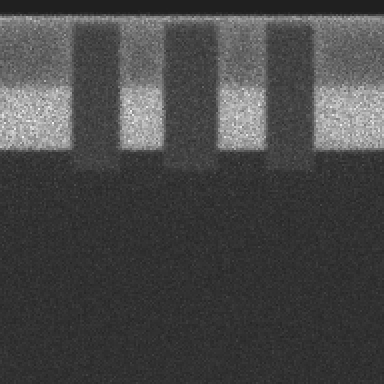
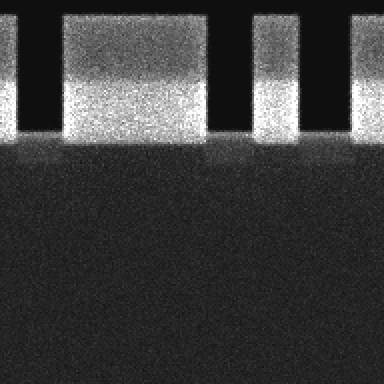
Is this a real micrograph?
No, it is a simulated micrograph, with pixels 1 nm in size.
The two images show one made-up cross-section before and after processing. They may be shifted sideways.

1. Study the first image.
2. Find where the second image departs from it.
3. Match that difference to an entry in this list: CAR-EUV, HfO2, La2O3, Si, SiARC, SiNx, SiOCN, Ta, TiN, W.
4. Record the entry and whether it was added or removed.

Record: SiARC / removed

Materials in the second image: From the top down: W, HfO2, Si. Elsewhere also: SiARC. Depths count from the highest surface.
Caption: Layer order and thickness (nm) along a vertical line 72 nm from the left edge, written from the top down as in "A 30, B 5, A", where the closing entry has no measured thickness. W 66, HfO2 62, Si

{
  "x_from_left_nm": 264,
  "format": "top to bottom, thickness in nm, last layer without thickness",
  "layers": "W 66, HfO2 62, Si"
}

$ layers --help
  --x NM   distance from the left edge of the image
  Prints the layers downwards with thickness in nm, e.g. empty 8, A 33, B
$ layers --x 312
empty 116, SiARC 32, Si